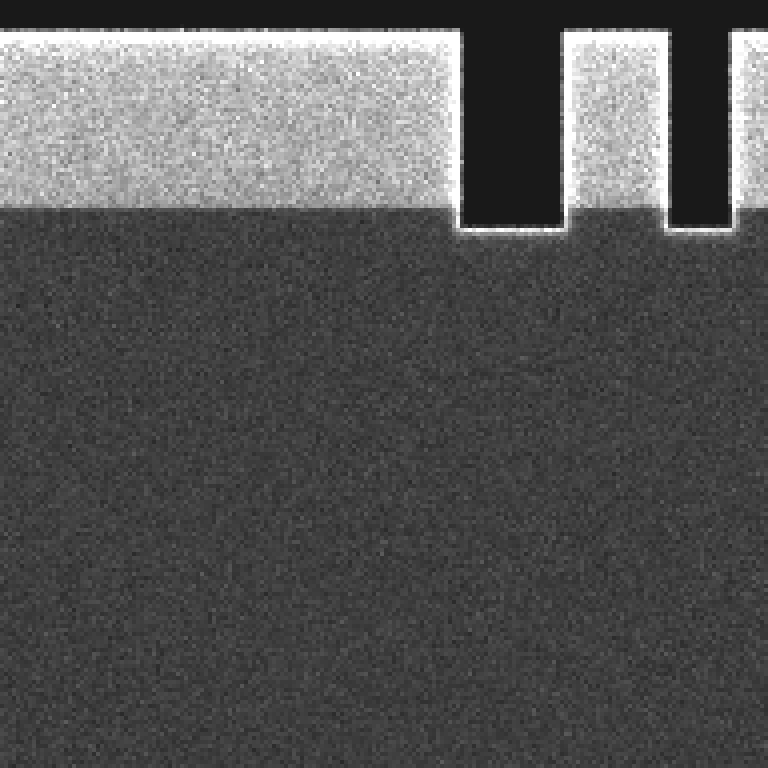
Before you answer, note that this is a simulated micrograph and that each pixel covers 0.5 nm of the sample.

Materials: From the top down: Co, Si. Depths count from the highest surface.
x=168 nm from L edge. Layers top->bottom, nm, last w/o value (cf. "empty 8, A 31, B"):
Co 88, Si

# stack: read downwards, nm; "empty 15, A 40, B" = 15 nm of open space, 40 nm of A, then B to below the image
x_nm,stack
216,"Co 88, Si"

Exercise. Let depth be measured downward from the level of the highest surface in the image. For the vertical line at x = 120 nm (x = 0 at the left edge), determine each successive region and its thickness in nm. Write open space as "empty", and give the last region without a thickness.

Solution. Co 88, Si